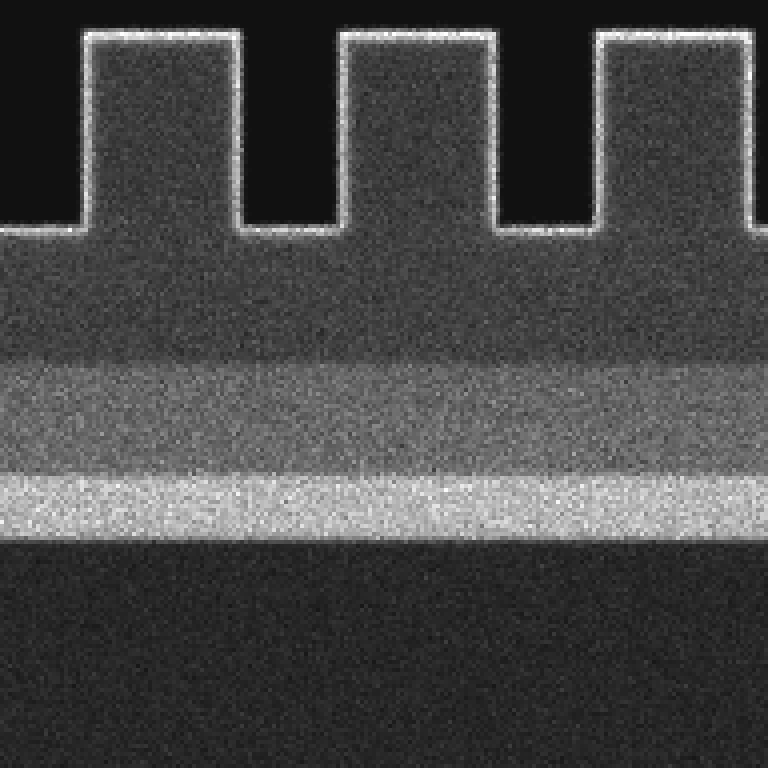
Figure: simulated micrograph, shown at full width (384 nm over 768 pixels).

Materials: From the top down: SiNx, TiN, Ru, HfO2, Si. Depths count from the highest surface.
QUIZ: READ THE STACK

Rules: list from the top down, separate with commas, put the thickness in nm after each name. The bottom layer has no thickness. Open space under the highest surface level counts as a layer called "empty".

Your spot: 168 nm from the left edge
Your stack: empty 98, TiN 68, Ru 56, HfO2 32, Si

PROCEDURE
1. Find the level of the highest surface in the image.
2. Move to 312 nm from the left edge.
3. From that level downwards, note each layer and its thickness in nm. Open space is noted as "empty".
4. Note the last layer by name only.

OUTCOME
SiNx 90, TiN 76, Ru 56, HfO2 32, Si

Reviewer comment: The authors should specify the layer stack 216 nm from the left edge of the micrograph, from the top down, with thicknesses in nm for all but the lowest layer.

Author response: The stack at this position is SiNx 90, TiN 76, Ru 56, HfO2 32, Si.